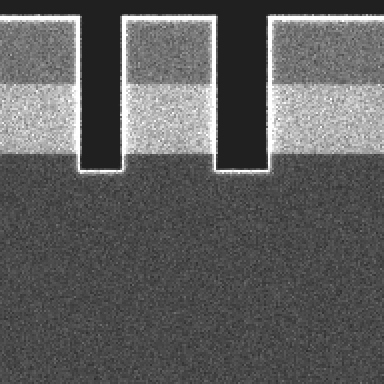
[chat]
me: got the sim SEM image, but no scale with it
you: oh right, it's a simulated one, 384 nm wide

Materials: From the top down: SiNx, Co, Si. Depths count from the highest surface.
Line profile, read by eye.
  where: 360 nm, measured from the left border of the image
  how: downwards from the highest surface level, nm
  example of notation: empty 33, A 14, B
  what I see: SiNx 68, Co 70, Si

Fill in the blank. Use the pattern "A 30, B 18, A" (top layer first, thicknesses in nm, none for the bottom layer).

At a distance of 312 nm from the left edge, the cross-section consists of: SiNx 68, Co 70, Si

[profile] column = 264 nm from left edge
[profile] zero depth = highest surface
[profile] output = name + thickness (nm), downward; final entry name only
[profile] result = empty 154, Si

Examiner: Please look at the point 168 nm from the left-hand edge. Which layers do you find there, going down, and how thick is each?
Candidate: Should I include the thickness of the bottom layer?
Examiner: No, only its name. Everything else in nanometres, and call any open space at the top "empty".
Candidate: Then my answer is SiNx 68, Co 70, Si